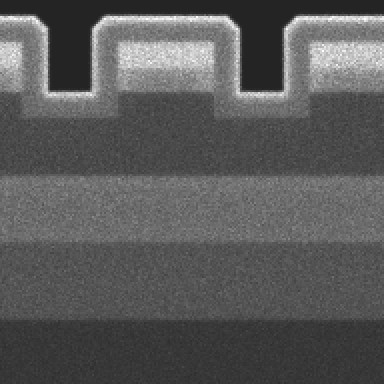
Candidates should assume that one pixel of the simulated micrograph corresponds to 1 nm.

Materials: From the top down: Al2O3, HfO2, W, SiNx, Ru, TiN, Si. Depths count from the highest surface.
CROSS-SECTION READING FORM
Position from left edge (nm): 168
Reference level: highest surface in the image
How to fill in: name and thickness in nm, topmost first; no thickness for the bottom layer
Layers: Al2O3 26, HfO2 26, W 24, SiNx 84, Ru 66, TiN 78, Si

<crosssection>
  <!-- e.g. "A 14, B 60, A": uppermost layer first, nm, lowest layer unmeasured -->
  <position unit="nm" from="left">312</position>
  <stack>Al2O3 26, HfO2 26, W 24, SiNx 84, Ru 66, TiN 78, Si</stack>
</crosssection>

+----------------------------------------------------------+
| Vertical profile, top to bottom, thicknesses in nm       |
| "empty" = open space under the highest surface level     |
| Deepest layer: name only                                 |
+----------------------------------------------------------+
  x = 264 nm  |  empty 76, Al2O3 26, SiNx 58, Ru 66, TiN 78, Si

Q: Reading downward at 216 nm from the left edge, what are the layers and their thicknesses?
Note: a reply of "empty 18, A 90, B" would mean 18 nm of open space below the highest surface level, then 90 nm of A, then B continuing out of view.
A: Al2O3 102, SiNx 58, Ru 66, TiN 78, Si